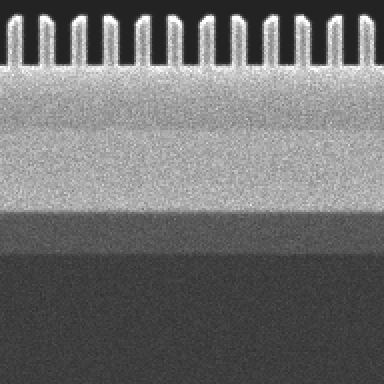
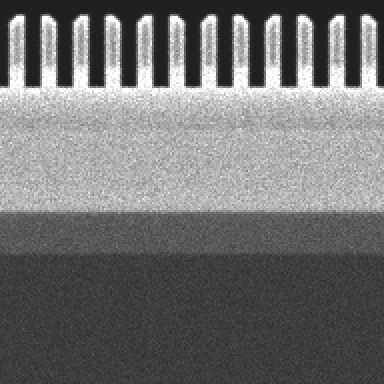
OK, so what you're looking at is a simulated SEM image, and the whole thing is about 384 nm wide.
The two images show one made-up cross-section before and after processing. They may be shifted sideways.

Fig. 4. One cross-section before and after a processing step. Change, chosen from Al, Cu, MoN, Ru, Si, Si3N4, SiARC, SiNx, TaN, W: Ru removed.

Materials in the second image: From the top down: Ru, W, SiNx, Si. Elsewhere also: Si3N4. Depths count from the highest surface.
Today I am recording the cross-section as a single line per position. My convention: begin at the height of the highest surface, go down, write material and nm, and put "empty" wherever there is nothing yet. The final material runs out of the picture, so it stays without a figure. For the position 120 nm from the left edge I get empty 72, Ru 42, W 82, SiNx 42, Si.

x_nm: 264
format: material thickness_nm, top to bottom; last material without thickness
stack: empty 72, Ru 42, W 82, SiNx 42, Si